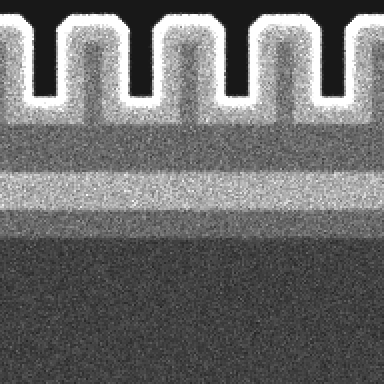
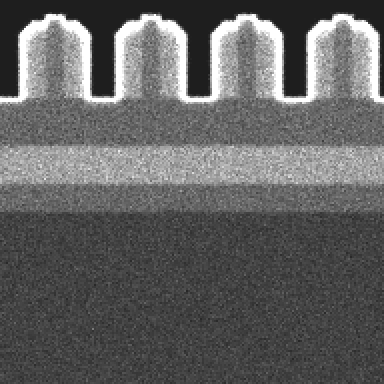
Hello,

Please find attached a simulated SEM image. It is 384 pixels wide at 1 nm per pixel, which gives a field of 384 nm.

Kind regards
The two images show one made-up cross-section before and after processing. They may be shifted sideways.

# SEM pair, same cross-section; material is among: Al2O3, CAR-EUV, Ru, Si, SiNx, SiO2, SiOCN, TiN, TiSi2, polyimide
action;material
removed;SiO2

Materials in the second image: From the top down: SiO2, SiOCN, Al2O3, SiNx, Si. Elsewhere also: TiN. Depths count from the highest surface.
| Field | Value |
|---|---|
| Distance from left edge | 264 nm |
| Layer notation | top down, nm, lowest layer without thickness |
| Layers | empty 6, SiO2 76, SiOCN 48, Al2O3 38, SiNx 28, Si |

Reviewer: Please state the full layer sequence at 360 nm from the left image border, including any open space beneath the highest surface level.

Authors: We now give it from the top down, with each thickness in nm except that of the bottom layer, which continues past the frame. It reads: empty 6, SiO2 76, SiOCN 48, Al2O3 38, SiNx 28, Si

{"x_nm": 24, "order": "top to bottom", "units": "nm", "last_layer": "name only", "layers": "empty 14, SiO2 68, SiOCN 48, Al2O3 38, SiNx 28, Si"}